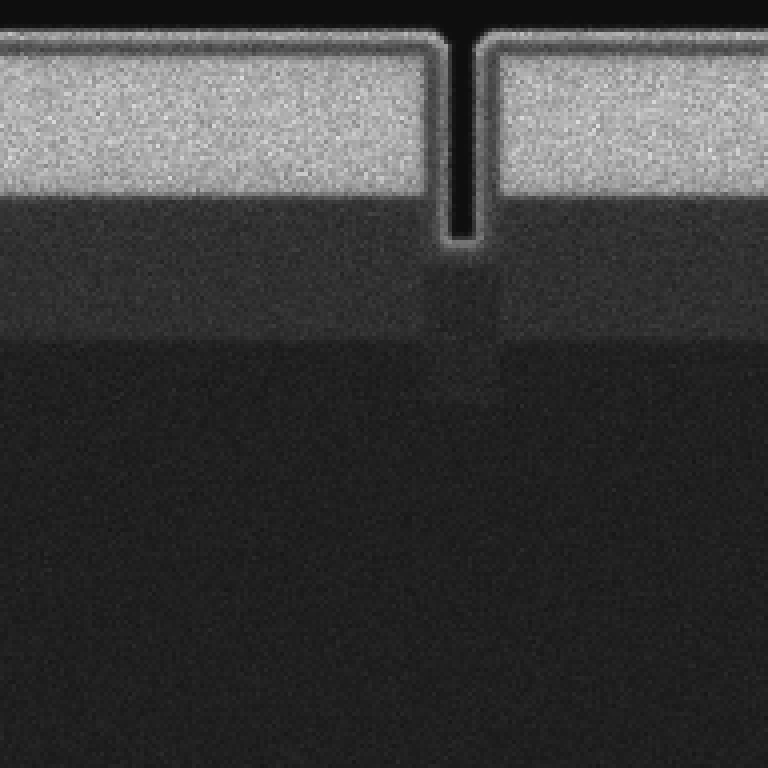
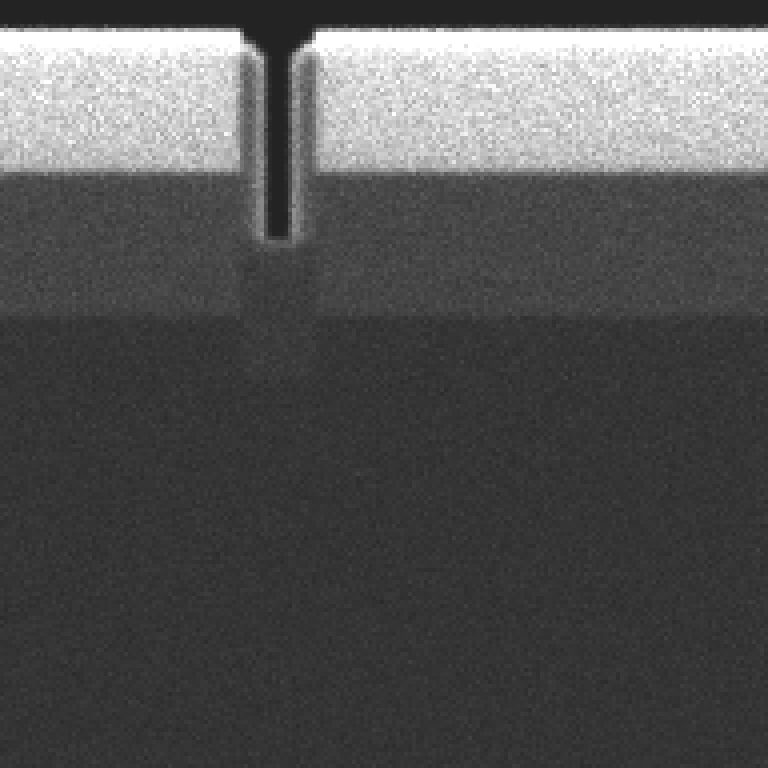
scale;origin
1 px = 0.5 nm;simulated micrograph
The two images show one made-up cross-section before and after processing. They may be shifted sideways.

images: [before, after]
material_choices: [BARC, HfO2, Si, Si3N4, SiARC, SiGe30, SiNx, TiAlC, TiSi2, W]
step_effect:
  removed: Si3N4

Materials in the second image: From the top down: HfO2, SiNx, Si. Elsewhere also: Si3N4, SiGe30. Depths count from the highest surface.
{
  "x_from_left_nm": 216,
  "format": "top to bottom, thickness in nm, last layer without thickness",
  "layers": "HfO2 70, SiNx 72, Si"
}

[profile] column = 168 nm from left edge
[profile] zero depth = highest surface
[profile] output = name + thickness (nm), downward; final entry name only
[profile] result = HfO2 70, SiNx 72, Si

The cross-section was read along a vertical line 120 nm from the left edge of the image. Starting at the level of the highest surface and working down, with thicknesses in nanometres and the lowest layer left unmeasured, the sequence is empty 6, Si3N4 98, SiGe30 70, Si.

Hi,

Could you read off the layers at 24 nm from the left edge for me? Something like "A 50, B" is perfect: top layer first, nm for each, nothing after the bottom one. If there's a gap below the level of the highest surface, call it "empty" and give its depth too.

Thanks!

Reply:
HfO2 70, SiNx 72, Si